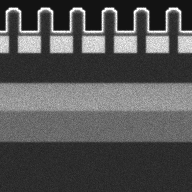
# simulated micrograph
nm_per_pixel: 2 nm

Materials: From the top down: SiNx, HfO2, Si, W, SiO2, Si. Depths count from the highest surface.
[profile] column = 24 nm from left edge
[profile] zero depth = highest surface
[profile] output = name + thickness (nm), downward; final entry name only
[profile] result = SiNx 10, Si 140, W 56, SiO2 62, Si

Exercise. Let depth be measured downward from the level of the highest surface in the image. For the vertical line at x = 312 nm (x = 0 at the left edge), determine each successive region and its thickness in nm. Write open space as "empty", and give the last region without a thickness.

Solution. empty 46, SiNx 10, HfO2 34, Si 60, W 56, SiO2 62, Si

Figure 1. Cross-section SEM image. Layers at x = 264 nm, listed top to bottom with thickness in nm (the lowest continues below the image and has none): empty 46, SiNx 10, HfO2 34, Si 60, W 56, SiO2 62, Si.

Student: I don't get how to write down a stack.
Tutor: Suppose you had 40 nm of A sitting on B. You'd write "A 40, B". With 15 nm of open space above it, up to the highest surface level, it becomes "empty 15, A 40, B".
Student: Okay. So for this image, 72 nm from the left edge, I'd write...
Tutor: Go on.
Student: empty 46, SiNx 10, HfO2 34, Si 60, W 56, SiO2 62, Si